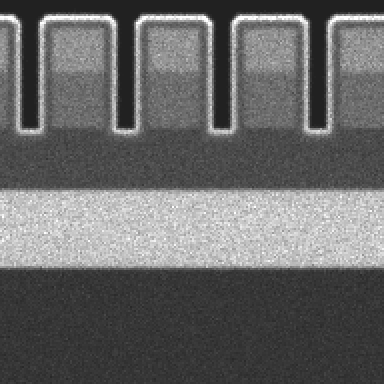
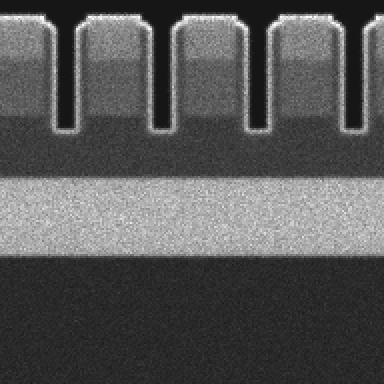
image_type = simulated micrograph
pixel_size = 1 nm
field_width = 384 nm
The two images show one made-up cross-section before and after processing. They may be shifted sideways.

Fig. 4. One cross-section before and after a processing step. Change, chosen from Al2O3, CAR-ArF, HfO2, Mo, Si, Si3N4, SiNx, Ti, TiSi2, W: Si3N4 removed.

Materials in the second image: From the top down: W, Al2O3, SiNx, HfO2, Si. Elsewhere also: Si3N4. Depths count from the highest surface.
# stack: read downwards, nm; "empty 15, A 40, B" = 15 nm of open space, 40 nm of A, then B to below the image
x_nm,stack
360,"empty 114, SiNx 48, HfO2 78, Si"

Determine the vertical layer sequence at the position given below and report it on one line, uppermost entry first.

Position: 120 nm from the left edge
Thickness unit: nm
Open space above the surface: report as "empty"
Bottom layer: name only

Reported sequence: W 44, Al2O3 56, SiNx 62, HfO2 78, Si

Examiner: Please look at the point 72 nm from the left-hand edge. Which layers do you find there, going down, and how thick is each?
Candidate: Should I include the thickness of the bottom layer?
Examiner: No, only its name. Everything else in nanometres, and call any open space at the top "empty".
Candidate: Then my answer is empty 114, SiNx 48, HfO2 78, Si